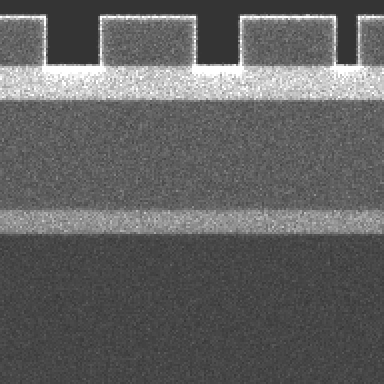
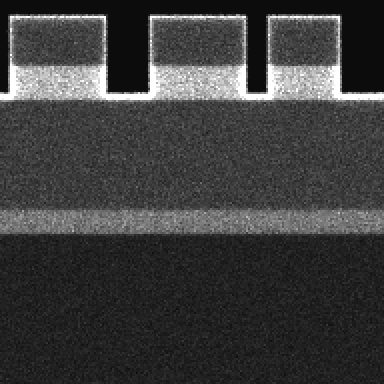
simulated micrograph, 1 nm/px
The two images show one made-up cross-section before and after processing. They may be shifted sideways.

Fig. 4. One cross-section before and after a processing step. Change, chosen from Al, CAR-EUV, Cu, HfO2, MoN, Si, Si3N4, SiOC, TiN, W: HfO2 removed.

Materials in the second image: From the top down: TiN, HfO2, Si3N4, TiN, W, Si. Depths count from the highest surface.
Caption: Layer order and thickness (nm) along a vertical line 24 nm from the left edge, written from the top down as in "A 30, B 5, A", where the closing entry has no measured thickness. TiN 50, HfO2 34, Si3N4 64, TiN 46, W 24, Si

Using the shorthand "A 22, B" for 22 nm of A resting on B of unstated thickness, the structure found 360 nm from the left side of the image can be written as empty 78, HfO2 6, Si3N4 64, TiN 46, W 24, Si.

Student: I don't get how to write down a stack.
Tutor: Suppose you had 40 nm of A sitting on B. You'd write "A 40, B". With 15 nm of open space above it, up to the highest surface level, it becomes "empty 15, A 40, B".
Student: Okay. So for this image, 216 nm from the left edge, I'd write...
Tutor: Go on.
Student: TiN 50, HfO2 34, Si3N4 64, TiN 46, W 24, Si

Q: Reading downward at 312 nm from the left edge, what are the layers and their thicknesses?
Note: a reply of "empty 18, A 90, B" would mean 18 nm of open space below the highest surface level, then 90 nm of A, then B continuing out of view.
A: TiN 50, HfO2 34, Si3N4 64, TiN 46, W 24, Si